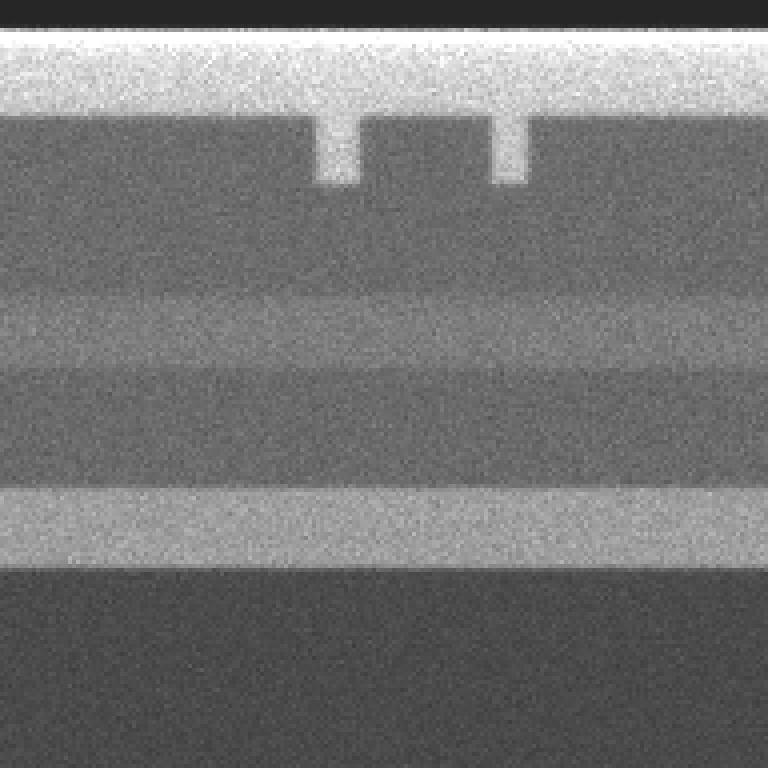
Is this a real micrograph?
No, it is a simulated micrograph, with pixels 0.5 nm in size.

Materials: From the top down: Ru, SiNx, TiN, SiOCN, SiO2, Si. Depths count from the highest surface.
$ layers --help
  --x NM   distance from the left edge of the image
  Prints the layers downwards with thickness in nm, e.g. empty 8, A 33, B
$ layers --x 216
Ru 42, SiNx 90, TiN 36, SiOCN 60, SiO2 40, Si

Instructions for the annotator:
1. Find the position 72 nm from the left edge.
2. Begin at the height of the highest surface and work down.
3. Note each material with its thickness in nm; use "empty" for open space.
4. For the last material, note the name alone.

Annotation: Ru 42, SiNx 90, TiN 36, SiOCN 60, SiO2 40, Si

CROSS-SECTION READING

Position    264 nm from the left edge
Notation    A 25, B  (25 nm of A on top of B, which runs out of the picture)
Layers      Ru 42, SiNx 90, TiN 36, SiOCN 60, SiO2 40, Si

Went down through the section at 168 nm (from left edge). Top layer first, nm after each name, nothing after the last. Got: Ru 76, SiNx 56, TiN 36, SiOCN 60, SiO2 40, Si